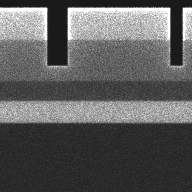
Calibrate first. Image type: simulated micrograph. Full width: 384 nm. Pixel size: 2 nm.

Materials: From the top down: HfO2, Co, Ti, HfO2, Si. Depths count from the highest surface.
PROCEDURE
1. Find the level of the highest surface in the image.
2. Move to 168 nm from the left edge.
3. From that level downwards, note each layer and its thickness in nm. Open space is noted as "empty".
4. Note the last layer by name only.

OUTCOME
HfO2 64, Co 82, Ti 40, HfO2 44, Si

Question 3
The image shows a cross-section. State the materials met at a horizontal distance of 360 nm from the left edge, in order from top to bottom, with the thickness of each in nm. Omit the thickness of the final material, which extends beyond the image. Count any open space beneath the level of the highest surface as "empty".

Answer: empty 116, Co 30, Ti 40, HfO2 44, Si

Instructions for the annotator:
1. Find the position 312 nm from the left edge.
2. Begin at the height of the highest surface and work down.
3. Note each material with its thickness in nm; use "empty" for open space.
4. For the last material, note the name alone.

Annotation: HfO2 64, Co 82, Ti 40, HfO2 44, Si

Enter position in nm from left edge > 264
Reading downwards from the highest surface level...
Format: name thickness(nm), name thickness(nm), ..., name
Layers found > HfO2 64, Co 82, Ti 40, HfO2 44, Si